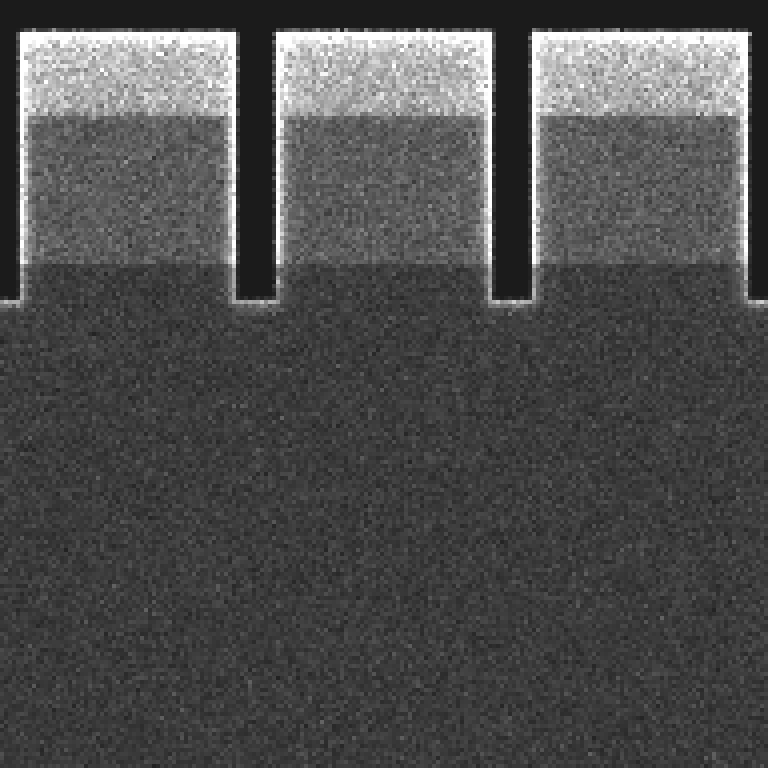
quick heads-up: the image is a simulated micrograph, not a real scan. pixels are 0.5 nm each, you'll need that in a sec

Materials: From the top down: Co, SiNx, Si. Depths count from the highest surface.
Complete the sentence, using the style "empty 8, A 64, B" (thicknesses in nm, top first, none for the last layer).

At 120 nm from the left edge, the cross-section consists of empty 134, Si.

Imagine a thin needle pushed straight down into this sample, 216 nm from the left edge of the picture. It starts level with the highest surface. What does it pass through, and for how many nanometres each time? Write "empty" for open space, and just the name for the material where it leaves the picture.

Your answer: Co 42, SiNx 74, Si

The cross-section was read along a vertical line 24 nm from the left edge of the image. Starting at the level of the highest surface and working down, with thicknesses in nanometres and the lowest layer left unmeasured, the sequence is Co 42, SiNx 74, Si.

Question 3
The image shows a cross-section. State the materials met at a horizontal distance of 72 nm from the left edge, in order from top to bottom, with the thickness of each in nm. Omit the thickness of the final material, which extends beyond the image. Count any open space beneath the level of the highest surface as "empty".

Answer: Co 42, SiNx 74, Si